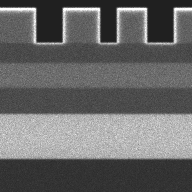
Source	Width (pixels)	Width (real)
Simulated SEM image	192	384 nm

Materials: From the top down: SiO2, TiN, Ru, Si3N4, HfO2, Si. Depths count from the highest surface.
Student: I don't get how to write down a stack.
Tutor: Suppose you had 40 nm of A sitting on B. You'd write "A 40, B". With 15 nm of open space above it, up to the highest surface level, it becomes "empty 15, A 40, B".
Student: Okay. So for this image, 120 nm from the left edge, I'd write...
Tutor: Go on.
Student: empty 70, TiN 40, Ru 50, Si3N4 52, HfO2 90, Si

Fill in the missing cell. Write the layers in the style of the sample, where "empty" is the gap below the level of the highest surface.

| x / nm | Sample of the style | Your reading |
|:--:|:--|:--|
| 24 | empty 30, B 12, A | SiO2 70, TiN 40, Ru 50, Si3N4 52, HfO2 90, Si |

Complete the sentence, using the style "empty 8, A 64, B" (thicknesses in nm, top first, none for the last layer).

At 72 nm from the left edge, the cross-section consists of empty 70, TiN 40, Ru 50, Si3N4 52, HfO2 90, Si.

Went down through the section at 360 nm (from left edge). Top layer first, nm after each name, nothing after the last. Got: SiO2 70, TiN 40, Ru 50, Si3N4 52, HfO2 90, Si